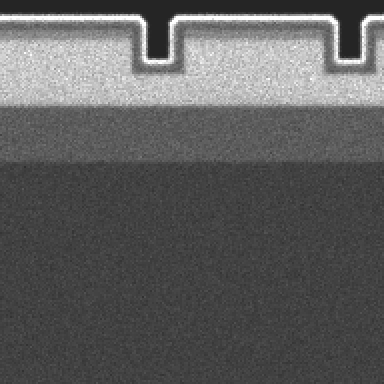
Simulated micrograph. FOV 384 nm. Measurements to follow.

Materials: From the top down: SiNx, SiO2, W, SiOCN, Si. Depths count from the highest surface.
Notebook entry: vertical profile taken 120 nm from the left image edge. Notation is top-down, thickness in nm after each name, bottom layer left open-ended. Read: SiNx 14, SiO2 10, W 66, SiOCN 56, Si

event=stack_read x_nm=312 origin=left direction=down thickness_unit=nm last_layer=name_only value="SiNx 14, SiO2 10, W 66, SiOCN 56, Si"